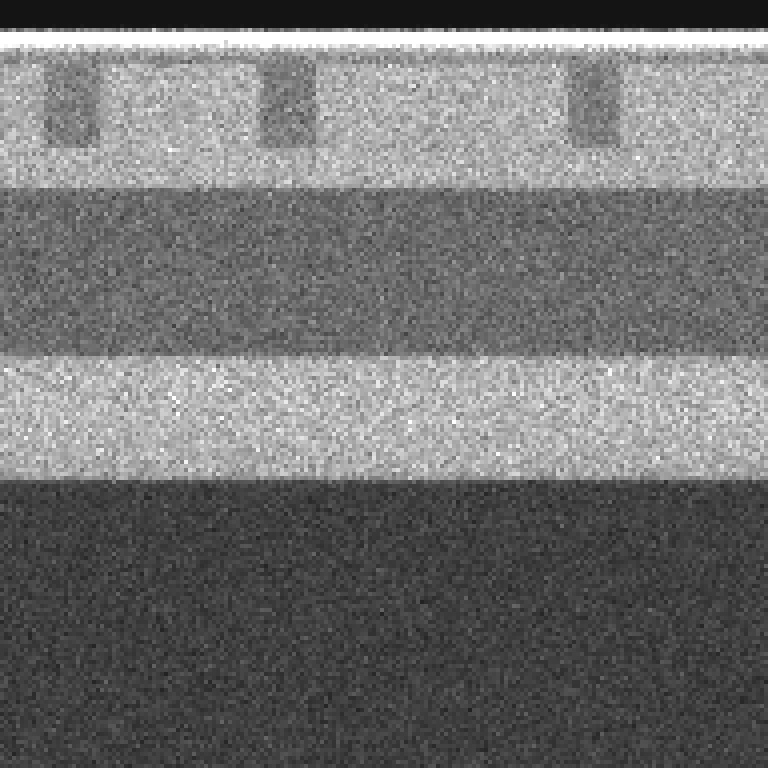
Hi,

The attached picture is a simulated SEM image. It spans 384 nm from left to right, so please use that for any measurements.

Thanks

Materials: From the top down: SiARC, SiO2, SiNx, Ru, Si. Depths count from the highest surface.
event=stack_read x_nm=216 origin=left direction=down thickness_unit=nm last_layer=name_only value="SiARC 16, SiO2 62, SiNx 84, Ru 62, Si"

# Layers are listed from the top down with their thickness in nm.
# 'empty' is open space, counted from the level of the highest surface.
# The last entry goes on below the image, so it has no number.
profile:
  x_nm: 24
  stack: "SiARC 58, SiO2 20, SiNx 84, Ru 62, Si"